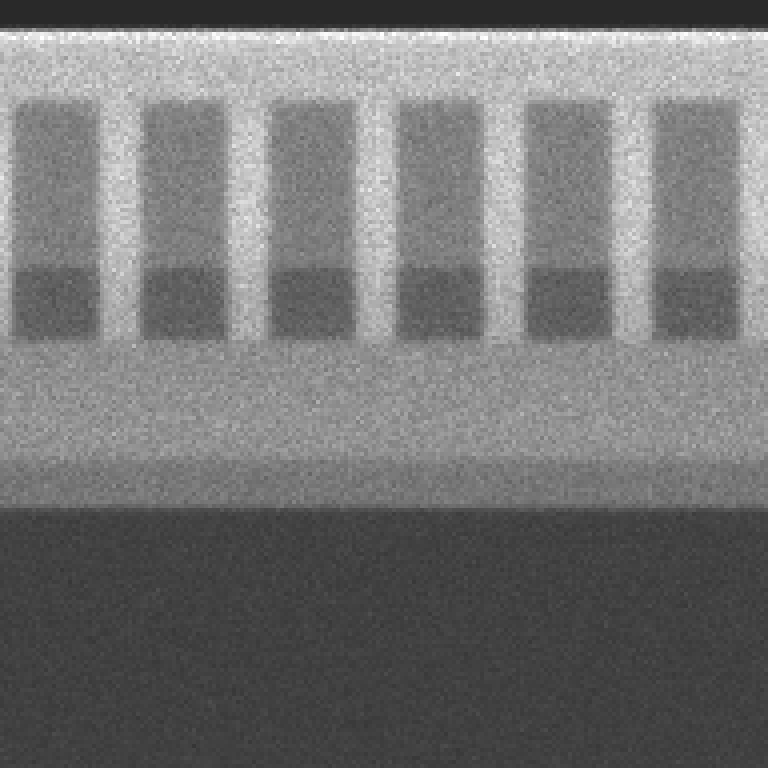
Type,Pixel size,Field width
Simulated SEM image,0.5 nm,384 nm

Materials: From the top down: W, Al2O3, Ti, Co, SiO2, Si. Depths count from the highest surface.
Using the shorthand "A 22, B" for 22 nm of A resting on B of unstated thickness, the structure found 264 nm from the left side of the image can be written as W 34, Al2O3 84, Ti 36, Co 60, SiO2 24, Si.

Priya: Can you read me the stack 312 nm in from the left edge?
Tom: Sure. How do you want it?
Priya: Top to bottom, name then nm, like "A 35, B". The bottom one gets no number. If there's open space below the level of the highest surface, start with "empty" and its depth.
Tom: W 154, Co 60, SiO2 24, Si